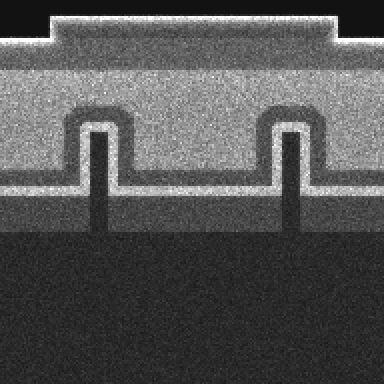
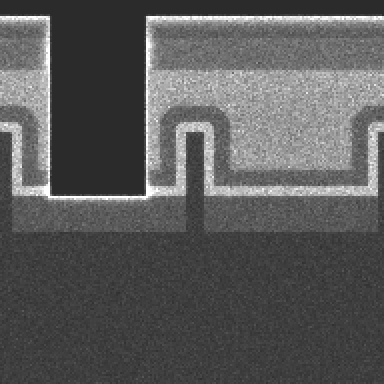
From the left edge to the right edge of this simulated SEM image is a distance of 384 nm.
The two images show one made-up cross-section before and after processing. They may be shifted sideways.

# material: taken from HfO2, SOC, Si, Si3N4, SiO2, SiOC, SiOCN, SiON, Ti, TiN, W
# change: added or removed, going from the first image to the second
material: HfO2 and SiO2 and TiN and W
change: removed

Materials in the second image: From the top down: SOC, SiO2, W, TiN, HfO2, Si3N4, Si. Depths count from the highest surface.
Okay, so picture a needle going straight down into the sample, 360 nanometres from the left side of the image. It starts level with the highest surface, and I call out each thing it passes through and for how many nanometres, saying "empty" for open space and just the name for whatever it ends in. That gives SOC 22, SiO2 32, W 40, TiN 76, HfO2 10, Si3N4 36, Si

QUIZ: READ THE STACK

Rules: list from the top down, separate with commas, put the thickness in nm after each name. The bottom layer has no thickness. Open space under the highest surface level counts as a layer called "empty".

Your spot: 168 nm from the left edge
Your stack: SOC 22, SiO2 32, W 40, TiN 76, HfO2 10, Si3N4 36, Si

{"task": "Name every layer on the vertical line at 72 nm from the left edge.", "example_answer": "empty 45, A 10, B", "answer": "empty 180, Si3N4 36, Si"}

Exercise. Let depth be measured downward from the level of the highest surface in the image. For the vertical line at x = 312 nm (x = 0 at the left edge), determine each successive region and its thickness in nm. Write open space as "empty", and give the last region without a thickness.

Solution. SOC 22, SiO2 32, W 100, TiN 16, HfO2 10, Si3N4 36, Si